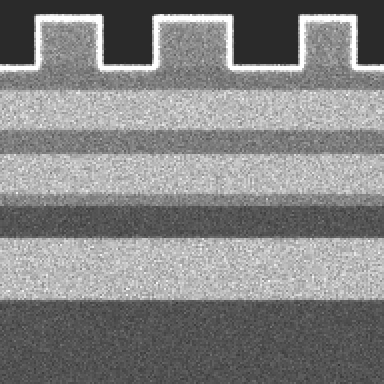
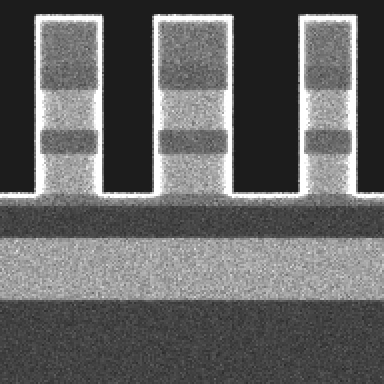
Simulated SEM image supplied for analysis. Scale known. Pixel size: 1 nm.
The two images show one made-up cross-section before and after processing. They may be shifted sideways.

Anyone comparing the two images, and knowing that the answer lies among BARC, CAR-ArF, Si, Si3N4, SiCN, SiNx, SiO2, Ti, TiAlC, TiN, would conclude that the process removed SiNx and SiO2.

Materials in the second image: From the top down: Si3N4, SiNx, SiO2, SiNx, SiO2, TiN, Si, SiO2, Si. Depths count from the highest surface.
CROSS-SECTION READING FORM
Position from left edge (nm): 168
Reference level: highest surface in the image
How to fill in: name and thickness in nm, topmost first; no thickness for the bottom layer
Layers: Si3N4 50, SiNx 24, SiO2 40, SiNx 24, SiO2 40, TiN 12, Si 32, SiO2 62, Si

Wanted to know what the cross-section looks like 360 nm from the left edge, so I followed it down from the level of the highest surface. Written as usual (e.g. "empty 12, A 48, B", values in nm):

empty 178, TiN 12, Si 32, SiO2 62, Si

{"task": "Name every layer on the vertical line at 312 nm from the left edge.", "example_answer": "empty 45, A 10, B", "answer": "Si3N4 50, SiNx 24, SiO2 40, SiNx 24, SiO2 40, TiN 12, Si 32, SiO2 62, Si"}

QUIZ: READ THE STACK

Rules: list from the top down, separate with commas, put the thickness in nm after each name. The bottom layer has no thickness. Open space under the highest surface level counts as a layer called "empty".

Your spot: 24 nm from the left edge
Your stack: empty 178, TiN 12, Si 32, SiO2 62, Si